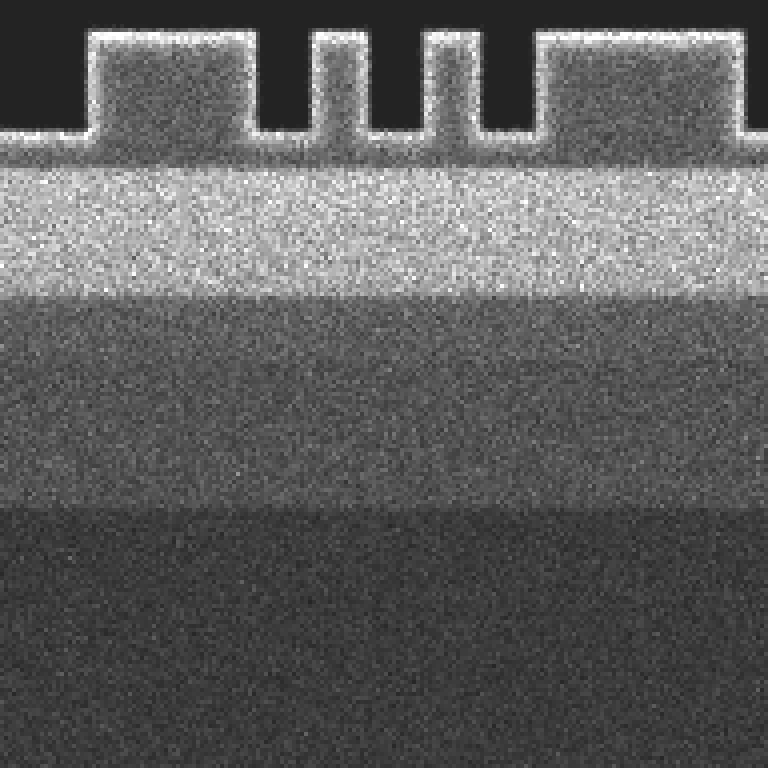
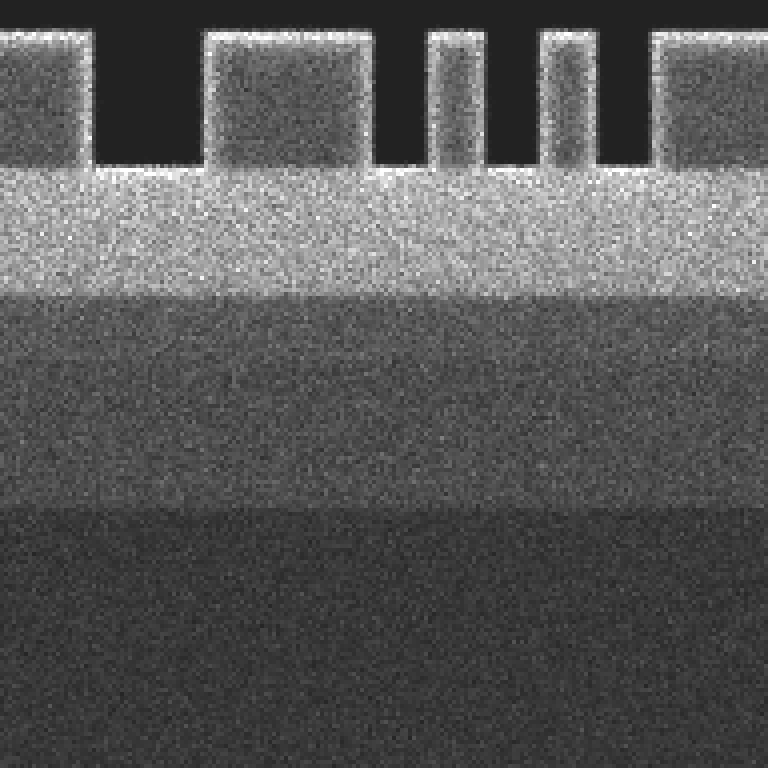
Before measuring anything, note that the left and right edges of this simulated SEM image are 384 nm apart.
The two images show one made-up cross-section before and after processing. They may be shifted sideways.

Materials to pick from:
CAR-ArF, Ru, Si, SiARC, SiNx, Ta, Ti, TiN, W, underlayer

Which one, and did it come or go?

underlayer - removed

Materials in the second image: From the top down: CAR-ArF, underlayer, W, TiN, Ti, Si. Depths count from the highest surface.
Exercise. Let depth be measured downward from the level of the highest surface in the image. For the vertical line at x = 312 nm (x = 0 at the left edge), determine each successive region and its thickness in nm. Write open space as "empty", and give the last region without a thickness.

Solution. empty 68, W 64, TiN 32, Ti 74, Si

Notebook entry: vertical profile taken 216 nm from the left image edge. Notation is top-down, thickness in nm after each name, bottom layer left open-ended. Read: CAR-ArF 50, underlayer 18, W 64, TiN 32, Ti 74, Si